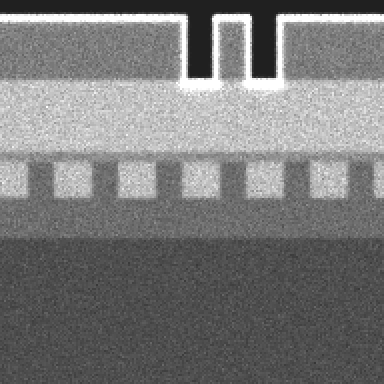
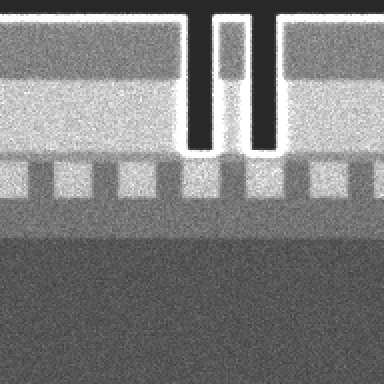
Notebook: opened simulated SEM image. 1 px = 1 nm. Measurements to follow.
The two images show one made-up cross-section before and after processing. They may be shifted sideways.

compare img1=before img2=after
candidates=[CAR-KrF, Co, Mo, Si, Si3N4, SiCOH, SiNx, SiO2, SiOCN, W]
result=removed:SiO2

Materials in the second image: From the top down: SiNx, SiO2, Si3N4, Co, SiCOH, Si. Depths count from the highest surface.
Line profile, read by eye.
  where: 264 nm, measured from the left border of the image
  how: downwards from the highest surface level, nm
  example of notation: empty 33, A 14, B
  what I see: empty 136, Si3N4 10, Co 36, SiCOH 40, Si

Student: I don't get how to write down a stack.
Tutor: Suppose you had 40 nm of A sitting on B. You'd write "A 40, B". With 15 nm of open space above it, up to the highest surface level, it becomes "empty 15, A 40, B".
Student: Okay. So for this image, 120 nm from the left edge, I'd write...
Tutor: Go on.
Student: SiNx 64, SiO2 72, Si3N4 10, Co 36, SiCOH 40, Si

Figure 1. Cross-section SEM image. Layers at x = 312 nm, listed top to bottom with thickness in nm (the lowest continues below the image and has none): SiNx 64, SiO2 72, Si3N4 10, Co 36, SiCOH 40, Si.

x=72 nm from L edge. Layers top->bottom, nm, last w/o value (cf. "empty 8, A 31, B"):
SiNx 64, SiO2 72, Si3N4 10, Co 36, SiCOH 40, Si